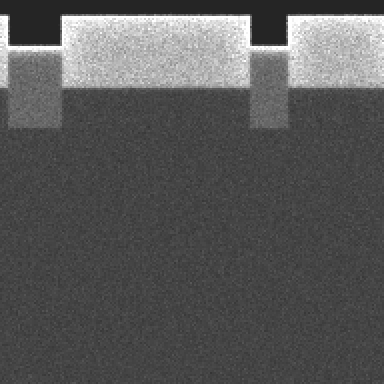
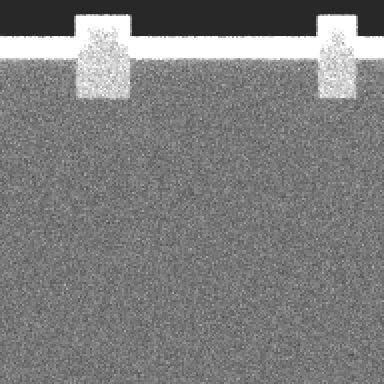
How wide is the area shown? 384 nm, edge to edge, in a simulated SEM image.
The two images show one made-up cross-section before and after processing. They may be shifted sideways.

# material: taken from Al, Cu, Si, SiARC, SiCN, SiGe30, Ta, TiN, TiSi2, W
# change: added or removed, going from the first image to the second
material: W
change: removed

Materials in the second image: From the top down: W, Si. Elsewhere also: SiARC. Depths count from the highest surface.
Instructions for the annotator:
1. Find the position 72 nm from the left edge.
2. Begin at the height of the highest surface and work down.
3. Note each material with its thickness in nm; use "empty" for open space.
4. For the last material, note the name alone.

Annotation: empty 22, W 20, Si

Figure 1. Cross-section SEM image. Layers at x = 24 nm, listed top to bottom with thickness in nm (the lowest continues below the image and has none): empty 22, W 20, Si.